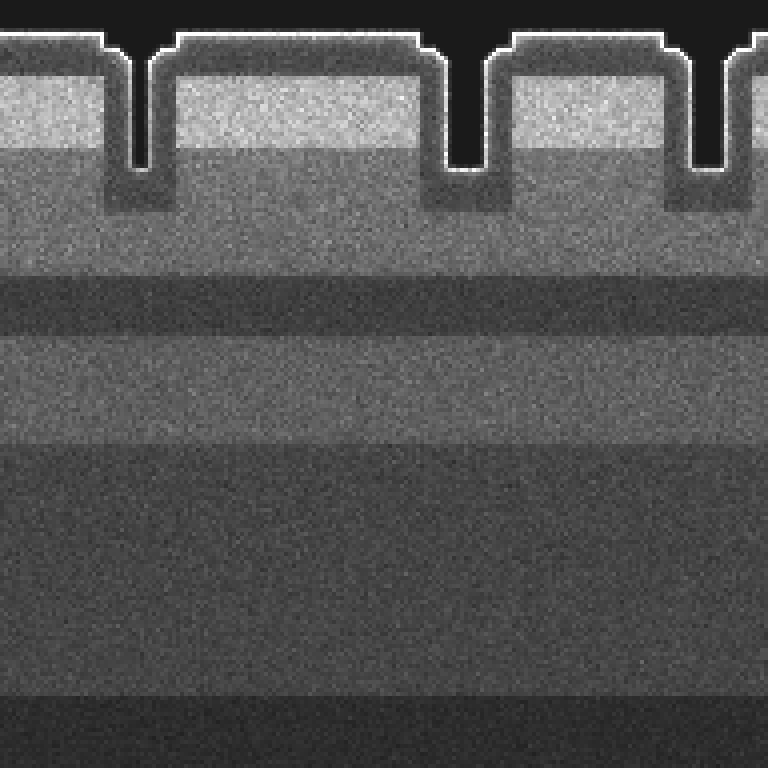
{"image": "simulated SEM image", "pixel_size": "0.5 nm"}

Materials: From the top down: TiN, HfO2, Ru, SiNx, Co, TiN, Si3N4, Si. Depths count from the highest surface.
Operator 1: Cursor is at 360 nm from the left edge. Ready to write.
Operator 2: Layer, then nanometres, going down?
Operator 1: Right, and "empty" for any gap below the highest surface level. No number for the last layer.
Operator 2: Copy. empty 68, TiN 22, Ru 32, SiNx 30, Co 54, TiN 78, Si3N4 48, Si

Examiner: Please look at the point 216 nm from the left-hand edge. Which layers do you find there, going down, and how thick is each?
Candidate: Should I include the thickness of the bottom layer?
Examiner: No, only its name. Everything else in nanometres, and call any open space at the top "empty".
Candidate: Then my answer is empty 8, TiN 82, Ru 32, SiNx 30, Co 54, TiN 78, Si3N4 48, Si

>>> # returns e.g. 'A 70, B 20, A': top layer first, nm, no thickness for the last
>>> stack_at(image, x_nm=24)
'TiN 22, HfO2 36, Ru 64, SiNx 30, Co 54, TiN 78, Si3N4 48, Si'